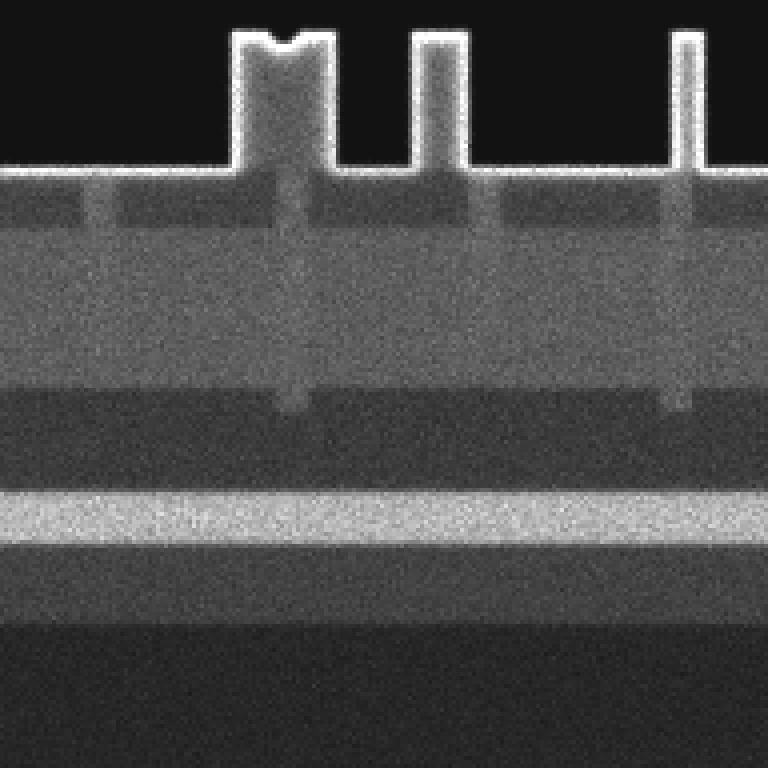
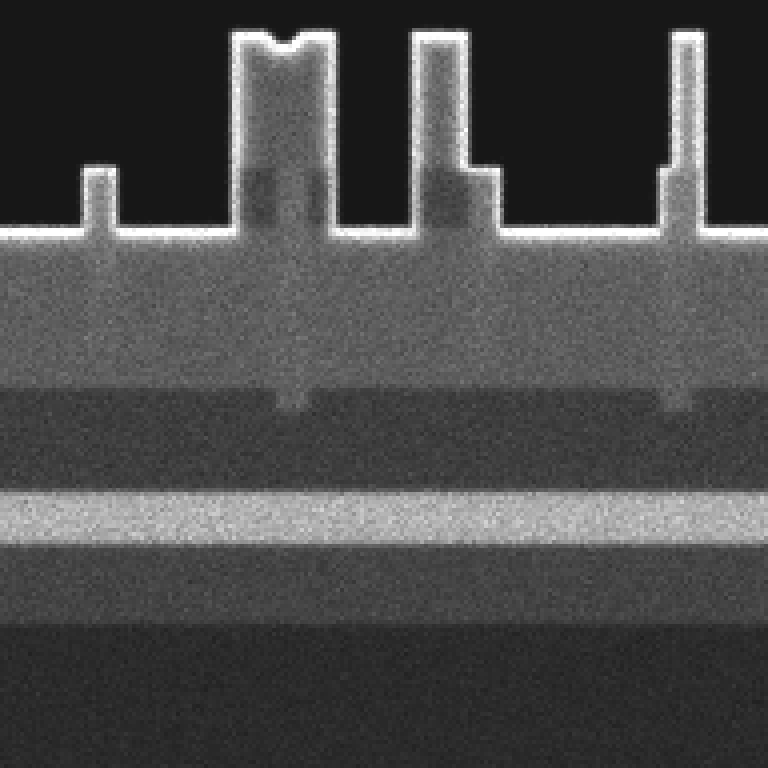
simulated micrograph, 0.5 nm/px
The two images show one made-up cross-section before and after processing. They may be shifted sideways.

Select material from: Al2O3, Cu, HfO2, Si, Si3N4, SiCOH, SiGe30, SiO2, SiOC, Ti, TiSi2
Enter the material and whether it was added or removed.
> Si3N4 / removed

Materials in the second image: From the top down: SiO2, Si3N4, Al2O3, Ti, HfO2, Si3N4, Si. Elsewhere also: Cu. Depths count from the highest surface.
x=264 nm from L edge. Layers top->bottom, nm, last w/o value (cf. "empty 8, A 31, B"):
empty 98, Al2O3 80, Ti 52, HfO2 26, Si3N4 40, Si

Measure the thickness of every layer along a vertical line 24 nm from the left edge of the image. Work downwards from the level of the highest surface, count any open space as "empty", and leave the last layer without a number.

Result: empty 98, Al2O3 80, Ti 52, HfO2 26, Si3N4 40, Si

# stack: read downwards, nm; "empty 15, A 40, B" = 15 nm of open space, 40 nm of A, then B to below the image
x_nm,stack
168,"empty 98, Al2O3 80, Ti 52, HfO2 26, Si3N4 40, Si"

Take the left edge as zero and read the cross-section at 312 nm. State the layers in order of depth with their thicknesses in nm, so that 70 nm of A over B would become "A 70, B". empty 98, Al2O3 80, Ti 52, HfO2 26, Si3N4 40, Si